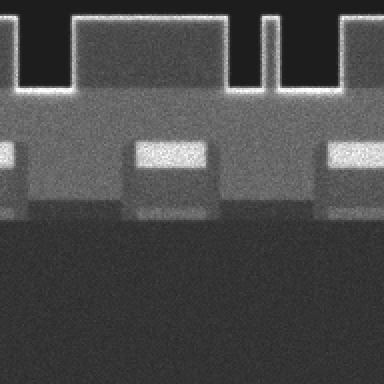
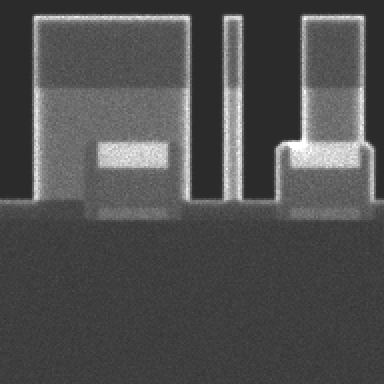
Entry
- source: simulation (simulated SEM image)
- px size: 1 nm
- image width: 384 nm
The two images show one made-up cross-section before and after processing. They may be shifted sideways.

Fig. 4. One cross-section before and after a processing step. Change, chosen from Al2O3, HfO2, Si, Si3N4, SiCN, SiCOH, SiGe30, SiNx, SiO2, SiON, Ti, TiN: SiO2 removed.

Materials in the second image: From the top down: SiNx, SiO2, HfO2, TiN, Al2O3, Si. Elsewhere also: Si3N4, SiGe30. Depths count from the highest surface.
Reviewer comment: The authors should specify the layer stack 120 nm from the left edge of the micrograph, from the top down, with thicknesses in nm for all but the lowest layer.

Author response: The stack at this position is SiNx 72, SiO2 54, HfO2 26, TiN 40, Al2O3 12, Si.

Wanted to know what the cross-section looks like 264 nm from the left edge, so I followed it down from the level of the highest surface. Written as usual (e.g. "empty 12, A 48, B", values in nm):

empty 184, SiGe30 20, Si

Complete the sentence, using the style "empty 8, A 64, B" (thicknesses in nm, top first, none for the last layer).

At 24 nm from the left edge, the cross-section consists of empty 184, SiGe30 20, Si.